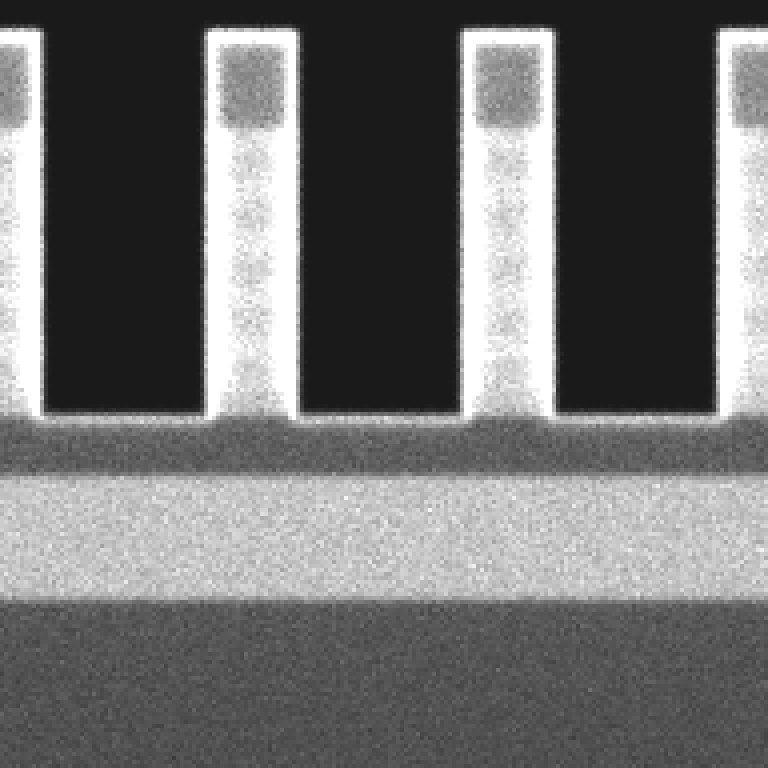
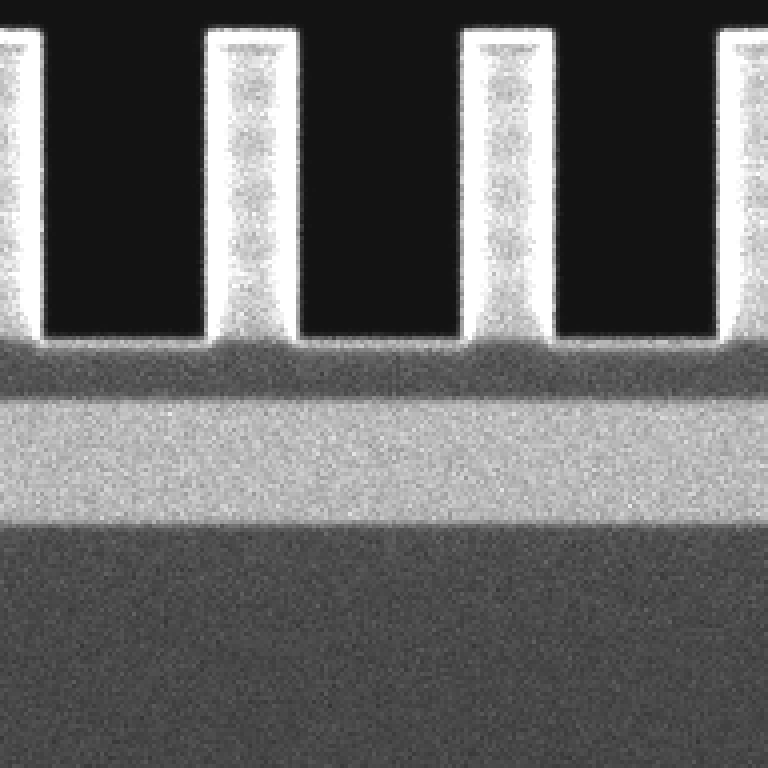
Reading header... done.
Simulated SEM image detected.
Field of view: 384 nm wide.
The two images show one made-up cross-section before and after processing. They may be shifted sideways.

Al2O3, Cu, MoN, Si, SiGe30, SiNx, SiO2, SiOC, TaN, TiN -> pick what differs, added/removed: SiNx removed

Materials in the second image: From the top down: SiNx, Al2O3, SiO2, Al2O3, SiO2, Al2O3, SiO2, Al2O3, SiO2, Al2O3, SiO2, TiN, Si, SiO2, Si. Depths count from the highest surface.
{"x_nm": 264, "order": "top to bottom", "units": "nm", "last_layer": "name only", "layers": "SiNx 10, Al2O3 12, SiO2 14, Al2O3 12, SiO2 14, Al2O3 12, SiO2 14, Al2O3 12, SiO2 14, Al2O3 12, SiO2 14, TiN 14, Si 30, SiO2 62, Si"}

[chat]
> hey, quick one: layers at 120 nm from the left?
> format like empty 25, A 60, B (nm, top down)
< SiNx 10, Al2O3 12, SiO2 14, Al2O3 12, SiO2 14, Al2O3 12, SiO2 14, Al2O3 12, SiO2 14, Al2O3 12, SiO2 14, TiN 14, Si 30, SiO2 62, Si